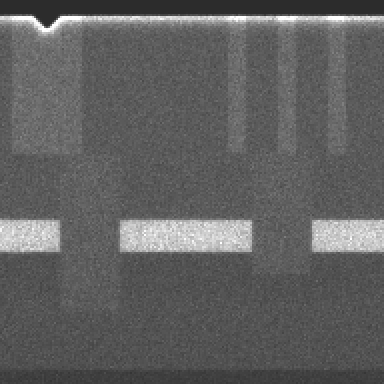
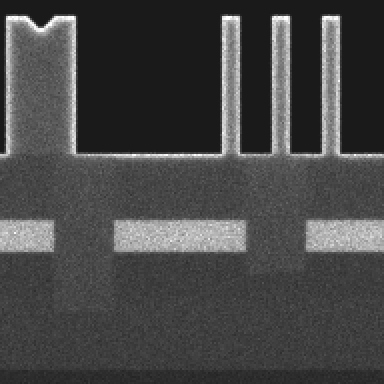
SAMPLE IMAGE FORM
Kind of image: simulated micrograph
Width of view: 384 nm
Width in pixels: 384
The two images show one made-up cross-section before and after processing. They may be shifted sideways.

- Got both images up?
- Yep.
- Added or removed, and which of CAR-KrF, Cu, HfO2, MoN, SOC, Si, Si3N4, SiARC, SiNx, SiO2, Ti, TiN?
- removed, SOC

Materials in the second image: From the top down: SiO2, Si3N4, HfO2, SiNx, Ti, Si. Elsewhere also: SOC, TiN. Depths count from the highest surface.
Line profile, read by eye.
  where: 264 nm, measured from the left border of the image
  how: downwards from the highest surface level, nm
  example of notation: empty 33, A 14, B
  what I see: empty 138, TiN 120, SiNx 22, Ti 74, Si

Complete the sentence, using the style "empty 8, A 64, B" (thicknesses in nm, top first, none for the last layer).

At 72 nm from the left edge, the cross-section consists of SiO2 138, TiN 158, Ti 58, Si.